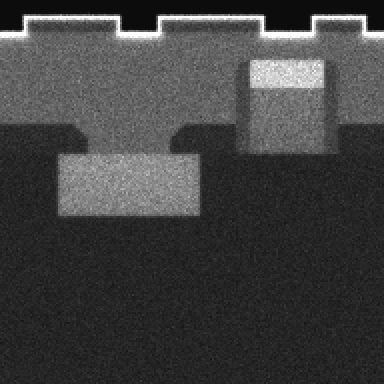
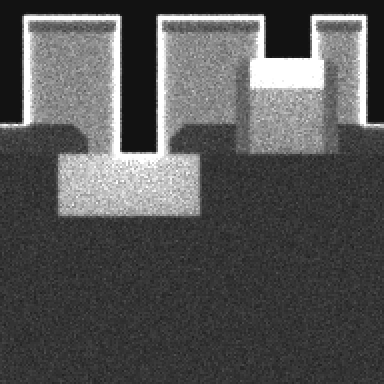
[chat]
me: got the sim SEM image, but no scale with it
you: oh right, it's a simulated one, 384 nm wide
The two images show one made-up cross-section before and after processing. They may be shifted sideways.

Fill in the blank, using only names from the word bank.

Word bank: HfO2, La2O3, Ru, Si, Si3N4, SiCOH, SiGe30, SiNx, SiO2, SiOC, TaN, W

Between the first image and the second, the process removed SiO2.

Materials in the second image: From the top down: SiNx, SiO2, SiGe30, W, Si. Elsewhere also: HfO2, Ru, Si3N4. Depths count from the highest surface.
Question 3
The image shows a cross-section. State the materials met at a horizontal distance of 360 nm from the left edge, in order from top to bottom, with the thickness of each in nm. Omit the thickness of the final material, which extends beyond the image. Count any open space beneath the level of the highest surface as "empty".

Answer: SiNx 16, SiO2 92, SiGe30 30, Si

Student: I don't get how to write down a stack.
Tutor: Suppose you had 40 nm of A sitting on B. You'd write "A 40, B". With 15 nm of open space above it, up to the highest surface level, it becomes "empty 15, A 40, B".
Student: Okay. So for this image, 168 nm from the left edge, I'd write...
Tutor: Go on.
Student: SiNx 16, SiO2 122, W 62, Si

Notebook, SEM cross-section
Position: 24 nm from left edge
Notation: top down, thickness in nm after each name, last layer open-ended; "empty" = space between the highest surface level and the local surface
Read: SiNx 16, SiO2 92, SiGe30 30, Si